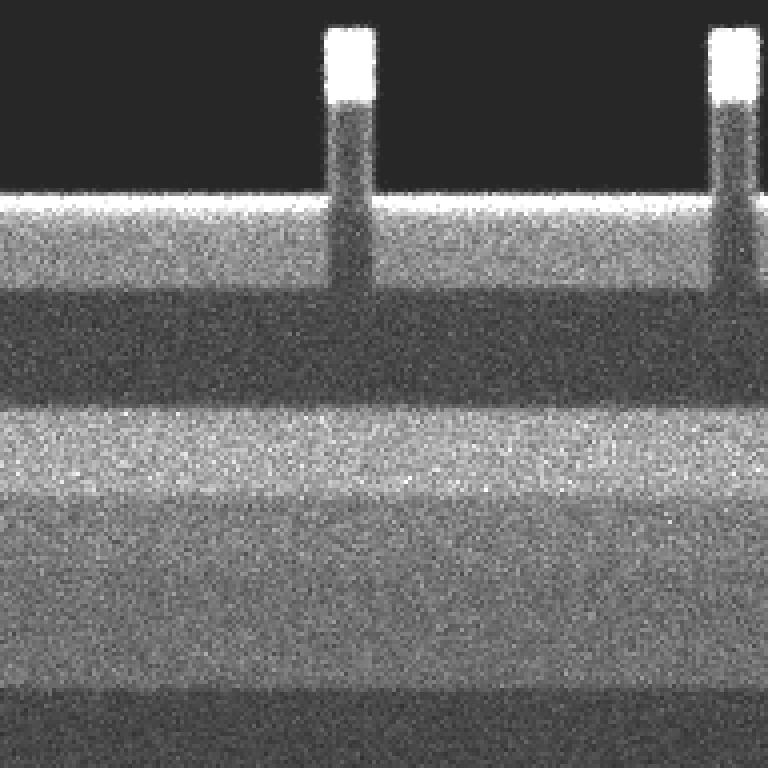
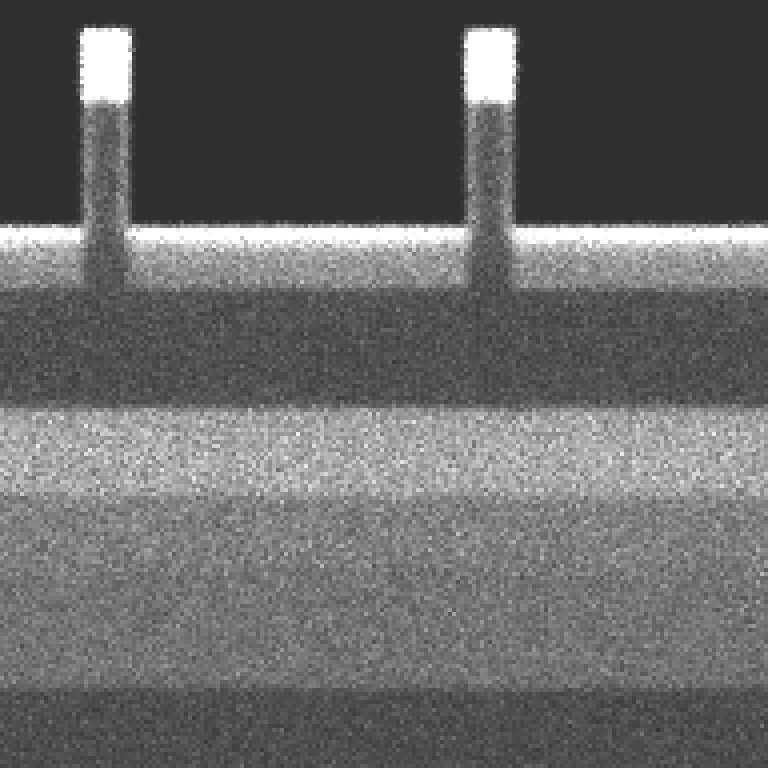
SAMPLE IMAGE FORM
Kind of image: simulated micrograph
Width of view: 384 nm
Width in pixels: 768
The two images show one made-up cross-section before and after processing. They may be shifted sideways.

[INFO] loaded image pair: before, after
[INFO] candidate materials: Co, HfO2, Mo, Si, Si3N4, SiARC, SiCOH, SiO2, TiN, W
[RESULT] removed SiO2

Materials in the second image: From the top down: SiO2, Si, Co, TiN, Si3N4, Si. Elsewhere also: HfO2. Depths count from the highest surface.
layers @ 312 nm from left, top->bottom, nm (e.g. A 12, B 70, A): empty 98, SiO2 30, Si 60, Co 44, TiN 36, Si3N4 60, Si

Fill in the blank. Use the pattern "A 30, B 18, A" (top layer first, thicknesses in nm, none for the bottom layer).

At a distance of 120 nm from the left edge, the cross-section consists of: empty 98, SiO2 30, Si 60, Co 44, TiN 36, Si3N4 60, Si